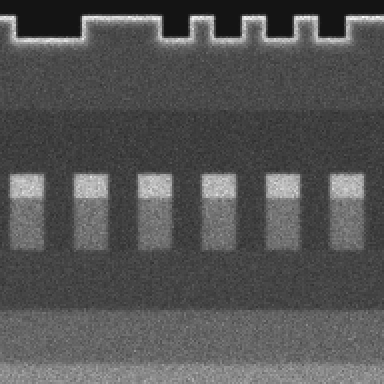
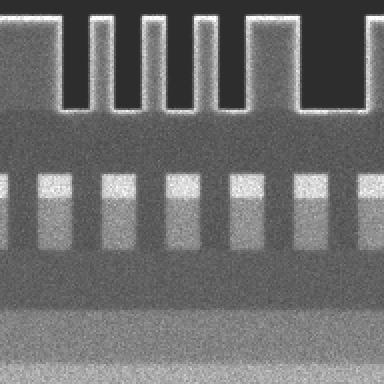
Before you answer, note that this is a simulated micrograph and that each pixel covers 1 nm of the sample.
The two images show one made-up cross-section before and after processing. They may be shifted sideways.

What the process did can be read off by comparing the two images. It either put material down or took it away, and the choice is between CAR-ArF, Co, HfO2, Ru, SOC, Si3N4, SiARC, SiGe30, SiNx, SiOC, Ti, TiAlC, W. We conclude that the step removed SOC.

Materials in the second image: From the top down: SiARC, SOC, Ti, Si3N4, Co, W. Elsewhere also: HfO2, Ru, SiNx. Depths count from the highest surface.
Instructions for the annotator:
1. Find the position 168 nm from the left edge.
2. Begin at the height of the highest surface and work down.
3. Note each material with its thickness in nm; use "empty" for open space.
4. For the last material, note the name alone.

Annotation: empty 94, SiNx 64, HfO2 24, Ru 52, Si3N4 60, Co 54, W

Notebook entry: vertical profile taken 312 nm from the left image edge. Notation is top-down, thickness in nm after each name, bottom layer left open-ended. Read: empty 94, SiNx 64, HfO2 24, Ru 52, Si3N4 60, Co 54, W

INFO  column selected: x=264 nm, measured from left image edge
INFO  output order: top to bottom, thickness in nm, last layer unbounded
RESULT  SiARC 22, SOC 72, Ti 140, Si3N4 60, Co 54, W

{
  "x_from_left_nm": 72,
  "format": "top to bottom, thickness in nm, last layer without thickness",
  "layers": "empty 94, Ti 140, Si3N4 60, Co 54, W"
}